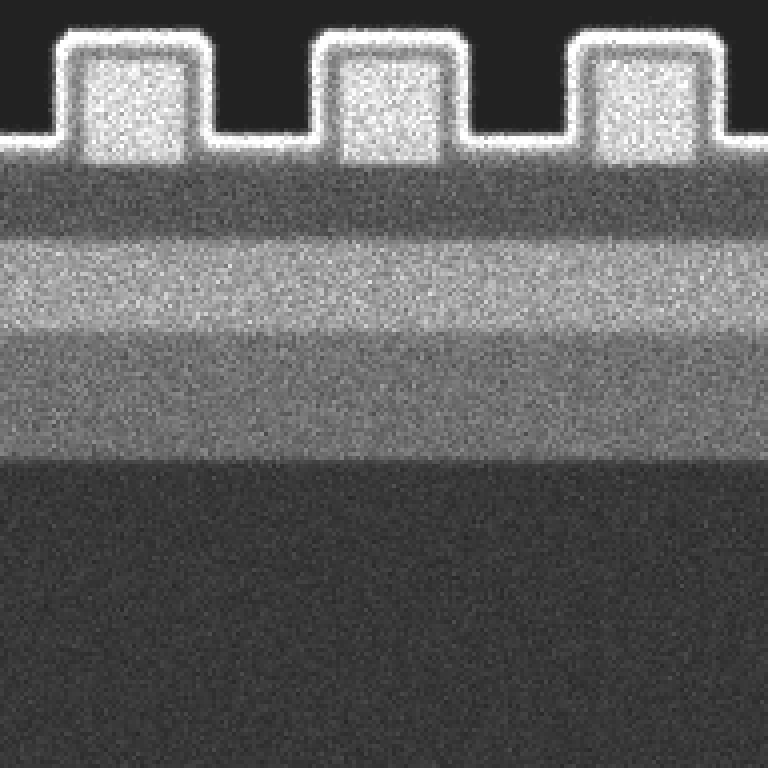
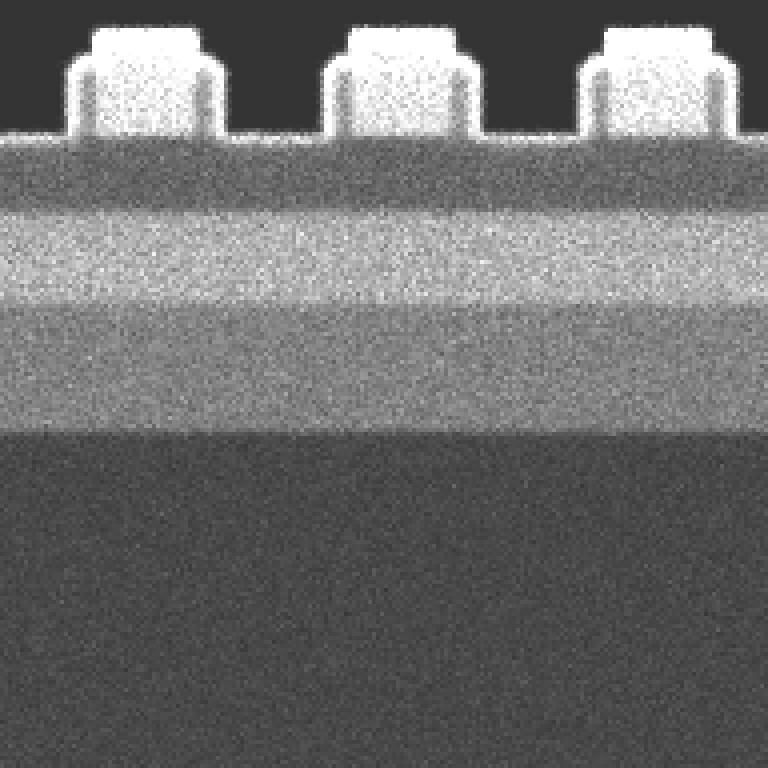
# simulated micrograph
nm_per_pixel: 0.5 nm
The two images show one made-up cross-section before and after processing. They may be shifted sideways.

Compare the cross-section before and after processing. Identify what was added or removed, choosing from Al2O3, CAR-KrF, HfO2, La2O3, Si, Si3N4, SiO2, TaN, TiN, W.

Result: SiO2 removed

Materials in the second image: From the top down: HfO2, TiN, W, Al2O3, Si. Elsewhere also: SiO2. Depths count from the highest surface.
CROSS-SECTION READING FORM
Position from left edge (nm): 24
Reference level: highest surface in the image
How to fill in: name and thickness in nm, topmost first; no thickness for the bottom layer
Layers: empty 52, TiN 38, W 46, Al2O3 64, Si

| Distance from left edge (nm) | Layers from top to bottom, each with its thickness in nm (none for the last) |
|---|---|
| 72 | HfO2 52, TiN 38, W 46, Al2O3 64, Si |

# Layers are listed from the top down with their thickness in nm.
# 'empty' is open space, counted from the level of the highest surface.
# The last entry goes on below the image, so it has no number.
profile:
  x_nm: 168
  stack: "empty 12, SiO2 40, TiN 38, W 46, Al2O3 64, Si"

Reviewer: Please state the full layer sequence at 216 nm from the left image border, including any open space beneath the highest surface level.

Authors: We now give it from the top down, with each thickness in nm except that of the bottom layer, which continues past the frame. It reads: HfO2 52, TiN 38, W 46, Al2O3 64, Si